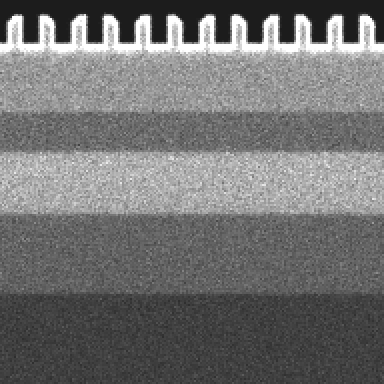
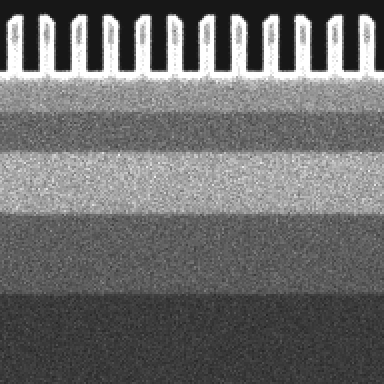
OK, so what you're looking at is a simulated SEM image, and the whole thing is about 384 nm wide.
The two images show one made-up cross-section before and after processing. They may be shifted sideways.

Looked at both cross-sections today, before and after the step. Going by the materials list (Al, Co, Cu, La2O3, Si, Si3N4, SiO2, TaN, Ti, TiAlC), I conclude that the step removed SiO2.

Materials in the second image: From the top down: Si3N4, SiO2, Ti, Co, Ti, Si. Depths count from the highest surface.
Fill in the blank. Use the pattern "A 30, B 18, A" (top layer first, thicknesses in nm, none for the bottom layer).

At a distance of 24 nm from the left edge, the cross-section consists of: empty 56, SiO2 40, Ti 40, Co 62, Ti 80, Si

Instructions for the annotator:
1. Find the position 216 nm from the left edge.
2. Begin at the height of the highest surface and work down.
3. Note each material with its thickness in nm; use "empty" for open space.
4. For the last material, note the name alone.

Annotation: empty 56, SiO2 40, Ti 40, Co 62, Ti 80, Si